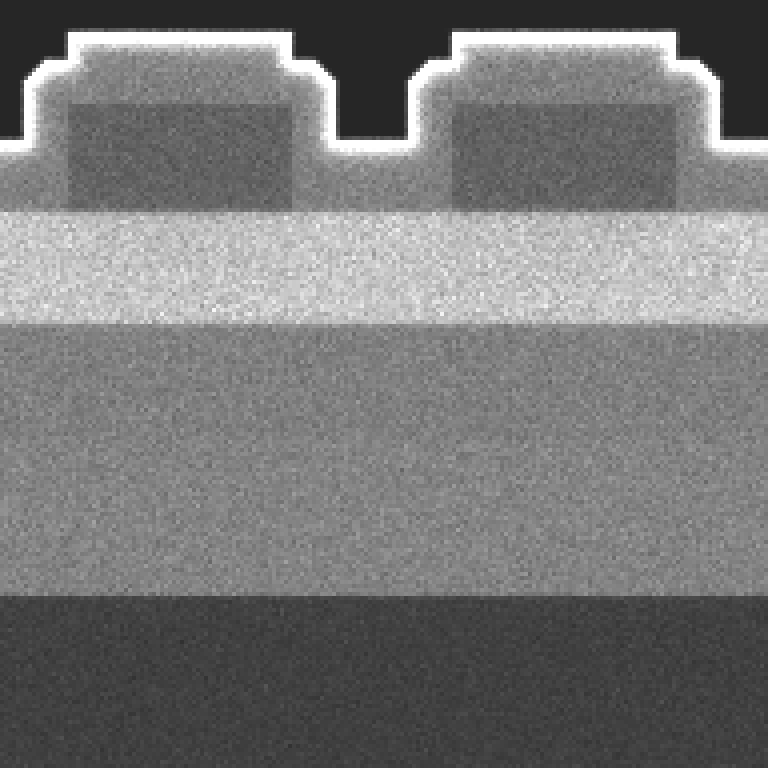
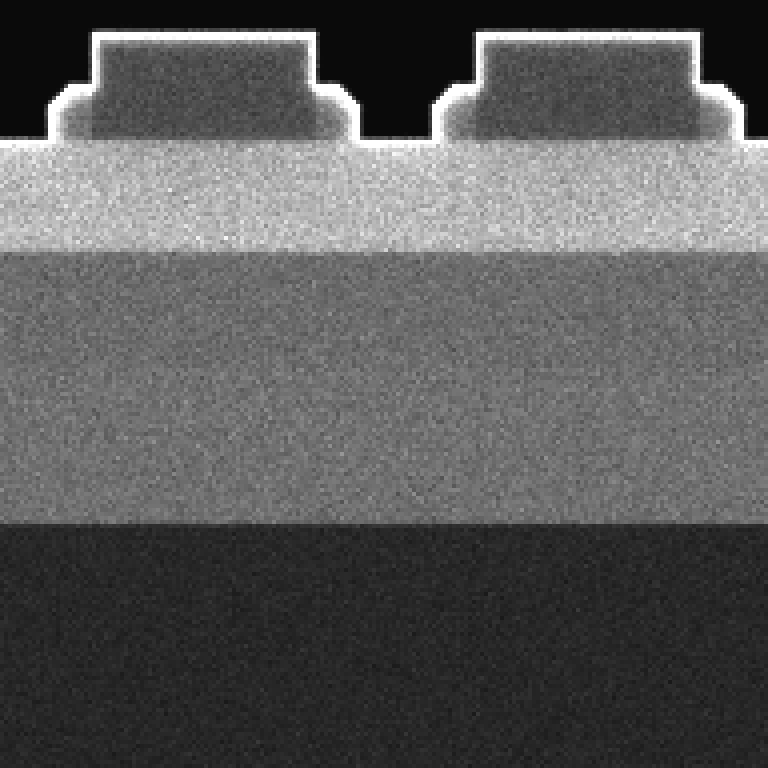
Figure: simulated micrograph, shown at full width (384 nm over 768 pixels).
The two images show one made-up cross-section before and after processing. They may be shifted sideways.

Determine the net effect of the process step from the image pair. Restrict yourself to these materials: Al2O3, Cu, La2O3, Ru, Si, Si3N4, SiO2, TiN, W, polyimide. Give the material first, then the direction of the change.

SiO2: removed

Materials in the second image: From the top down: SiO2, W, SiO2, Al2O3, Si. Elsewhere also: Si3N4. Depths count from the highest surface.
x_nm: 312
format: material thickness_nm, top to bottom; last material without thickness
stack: Si3N4 54, W 56, SiO2 58, Al2O3 78, Si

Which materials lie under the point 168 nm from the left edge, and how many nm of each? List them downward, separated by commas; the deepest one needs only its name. empty 26, SiO2 28, W 56, SiO2 58, Al2O3 78, Si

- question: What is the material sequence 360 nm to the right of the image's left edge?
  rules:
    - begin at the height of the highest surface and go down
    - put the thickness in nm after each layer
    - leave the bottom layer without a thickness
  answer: empty 26, SiO2 28, W 56, SiO2 58, Al2O3 78, Si